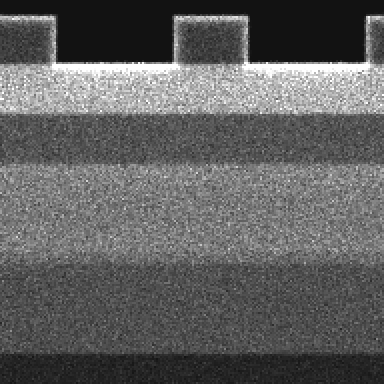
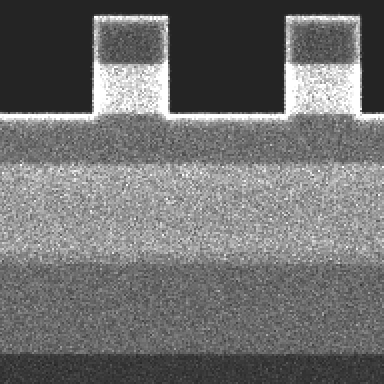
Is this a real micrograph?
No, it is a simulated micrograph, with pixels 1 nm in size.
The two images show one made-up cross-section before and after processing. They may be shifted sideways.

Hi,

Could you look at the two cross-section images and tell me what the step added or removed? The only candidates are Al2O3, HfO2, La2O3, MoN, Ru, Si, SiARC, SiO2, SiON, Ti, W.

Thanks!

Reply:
removed HfO2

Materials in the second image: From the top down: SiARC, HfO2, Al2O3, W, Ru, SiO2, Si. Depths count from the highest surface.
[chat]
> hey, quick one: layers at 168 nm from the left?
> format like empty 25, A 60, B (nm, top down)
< empty 98, Al2O3 50, W 88, Ru 12, SiO2 90, Si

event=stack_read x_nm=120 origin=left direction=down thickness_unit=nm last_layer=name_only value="SiARC 48, HfO2 50, Al2O3 50, W 88, Ru 12, SiO2 90, Si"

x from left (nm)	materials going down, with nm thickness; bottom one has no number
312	SiARC 48, HfO2 50, Al2O3 50, W 88, Ru 12, SiO2 90, Si